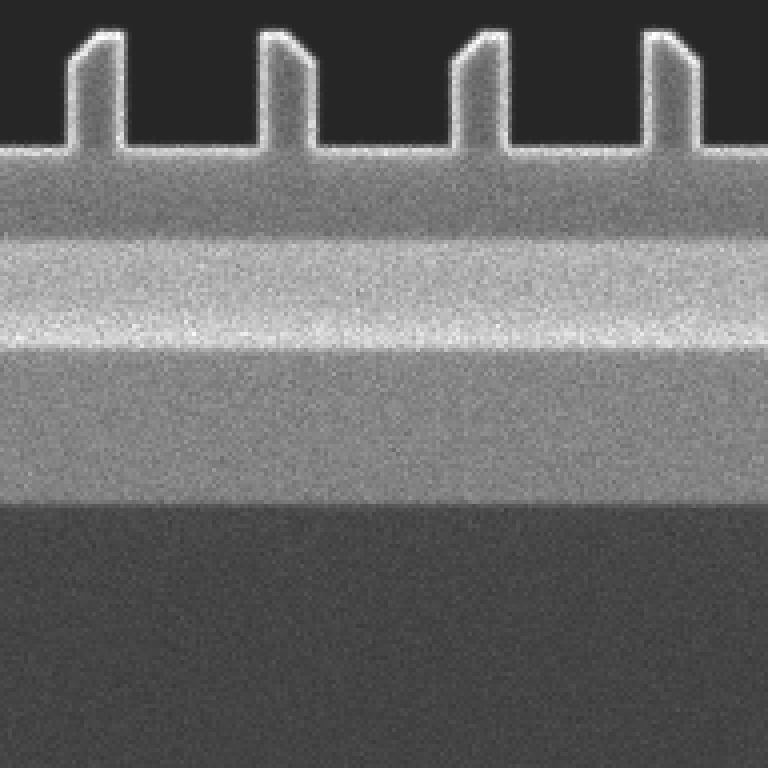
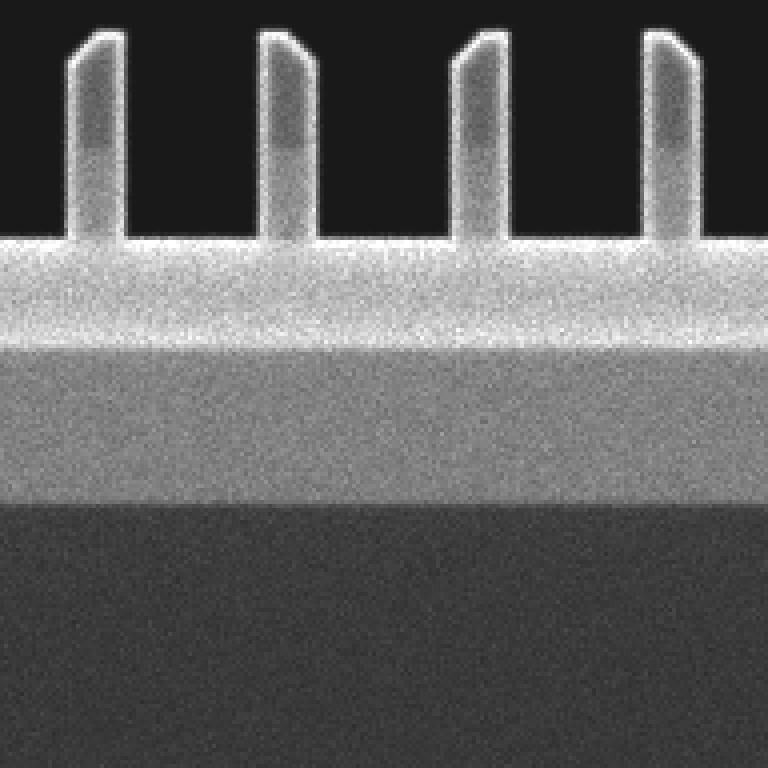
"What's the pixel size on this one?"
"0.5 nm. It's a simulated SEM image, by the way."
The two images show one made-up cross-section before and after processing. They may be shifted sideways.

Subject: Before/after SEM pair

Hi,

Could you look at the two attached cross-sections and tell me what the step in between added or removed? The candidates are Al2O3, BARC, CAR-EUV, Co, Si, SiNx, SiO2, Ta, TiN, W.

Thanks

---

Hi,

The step removed TiN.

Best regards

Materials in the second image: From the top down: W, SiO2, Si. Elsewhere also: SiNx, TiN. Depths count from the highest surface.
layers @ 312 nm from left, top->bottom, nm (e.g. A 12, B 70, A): empty 104, W 54, SiO2 78, Si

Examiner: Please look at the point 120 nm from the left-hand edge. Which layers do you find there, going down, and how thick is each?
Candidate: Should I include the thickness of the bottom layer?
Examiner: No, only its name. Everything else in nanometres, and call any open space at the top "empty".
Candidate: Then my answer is empty 104, W 54, SiO2 78, Si